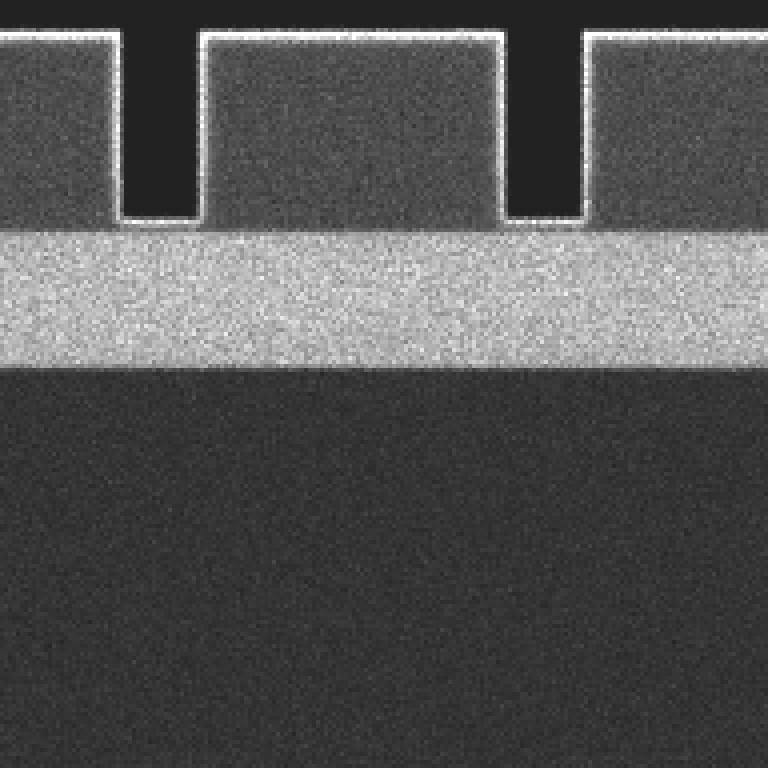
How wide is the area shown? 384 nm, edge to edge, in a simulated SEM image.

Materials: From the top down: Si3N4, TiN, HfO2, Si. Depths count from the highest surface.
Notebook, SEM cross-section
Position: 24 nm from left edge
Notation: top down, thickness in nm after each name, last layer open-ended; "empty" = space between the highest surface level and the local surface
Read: Si3N4 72, TiN 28, HfO2 68, Si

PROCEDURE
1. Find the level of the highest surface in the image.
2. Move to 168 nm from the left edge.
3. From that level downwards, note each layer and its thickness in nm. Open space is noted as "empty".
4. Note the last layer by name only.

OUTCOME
Si3N4 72, TiN 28, HfO2 68, Si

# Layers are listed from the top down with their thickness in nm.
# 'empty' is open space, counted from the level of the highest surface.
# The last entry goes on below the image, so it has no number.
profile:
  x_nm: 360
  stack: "Si3N4 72, TiN 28, HfO2 68, Si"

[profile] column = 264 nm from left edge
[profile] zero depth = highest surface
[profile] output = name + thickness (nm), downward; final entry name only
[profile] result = empty 94, TiN 6, HfO2 68, Si